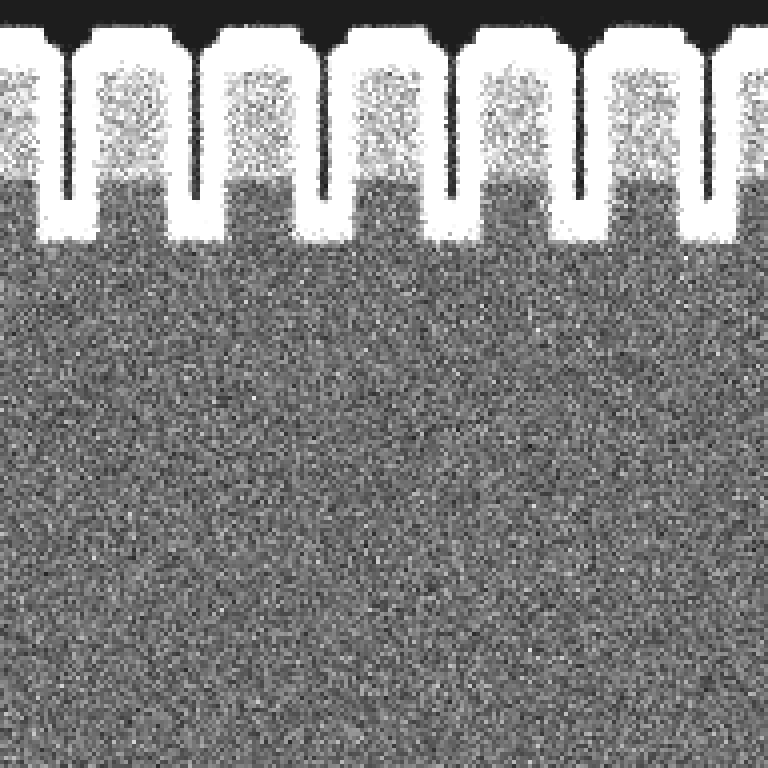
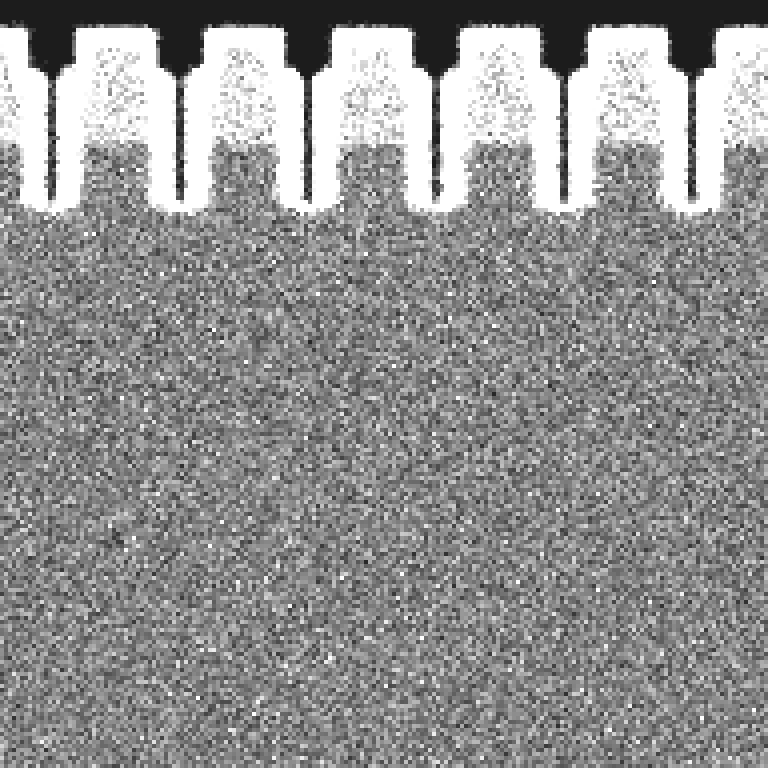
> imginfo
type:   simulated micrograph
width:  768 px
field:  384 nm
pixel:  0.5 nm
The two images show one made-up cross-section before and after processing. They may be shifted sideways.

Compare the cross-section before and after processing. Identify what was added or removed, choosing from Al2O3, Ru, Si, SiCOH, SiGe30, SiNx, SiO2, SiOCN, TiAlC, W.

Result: SiO2 removed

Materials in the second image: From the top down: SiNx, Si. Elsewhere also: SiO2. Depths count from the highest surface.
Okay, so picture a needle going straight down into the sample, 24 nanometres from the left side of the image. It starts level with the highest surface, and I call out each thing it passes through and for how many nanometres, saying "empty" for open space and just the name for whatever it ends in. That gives empty 86, Si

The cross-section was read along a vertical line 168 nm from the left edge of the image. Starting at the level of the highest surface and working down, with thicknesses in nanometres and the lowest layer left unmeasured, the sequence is SiNx 56, Si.